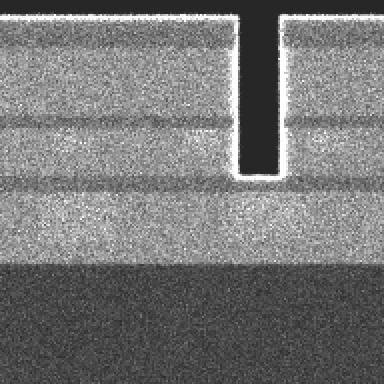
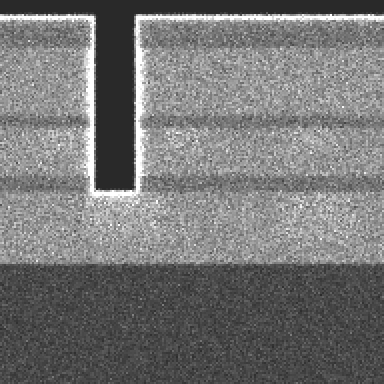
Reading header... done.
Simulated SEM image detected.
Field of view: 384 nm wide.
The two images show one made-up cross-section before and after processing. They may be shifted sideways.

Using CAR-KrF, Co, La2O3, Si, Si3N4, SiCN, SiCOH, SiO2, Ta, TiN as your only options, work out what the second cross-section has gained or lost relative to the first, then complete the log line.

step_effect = removed Si3N4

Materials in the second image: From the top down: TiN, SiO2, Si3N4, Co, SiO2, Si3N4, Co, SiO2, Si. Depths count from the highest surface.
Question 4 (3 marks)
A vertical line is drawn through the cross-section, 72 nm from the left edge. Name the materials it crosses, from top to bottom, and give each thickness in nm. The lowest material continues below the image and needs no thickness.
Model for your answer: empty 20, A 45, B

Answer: TiN 32, SiO2 68, Si3N4 12, Co 24, SiO2 24, Si3N4 16, SiO2 72, Si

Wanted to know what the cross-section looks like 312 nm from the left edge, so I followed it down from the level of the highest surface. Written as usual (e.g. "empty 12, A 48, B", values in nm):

TiN 32, SiO2 68, Si3N4 12, Co 24, SiO2 24, Si3N4 16, Co 50, SiO2 22, Si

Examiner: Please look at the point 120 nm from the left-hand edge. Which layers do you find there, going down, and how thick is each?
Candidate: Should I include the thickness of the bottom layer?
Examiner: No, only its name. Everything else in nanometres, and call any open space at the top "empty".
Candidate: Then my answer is empty 176, Co 50, SiO2 22, Si